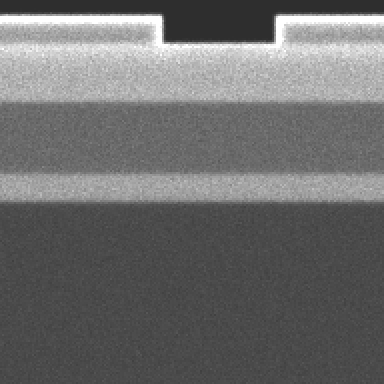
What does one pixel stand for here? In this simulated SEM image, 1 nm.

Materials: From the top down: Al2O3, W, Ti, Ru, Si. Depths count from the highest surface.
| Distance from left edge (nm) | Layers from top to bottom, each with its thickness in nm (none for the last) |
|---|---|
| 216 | empty 28, W 58, Ti 72, Ru 28, Si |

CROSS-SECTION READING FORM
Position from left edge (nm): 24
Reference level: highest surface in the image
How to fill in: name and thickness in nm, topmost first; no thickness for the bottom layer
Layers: Al2O3 28, W 58, Ti 72, Ru 28, Si